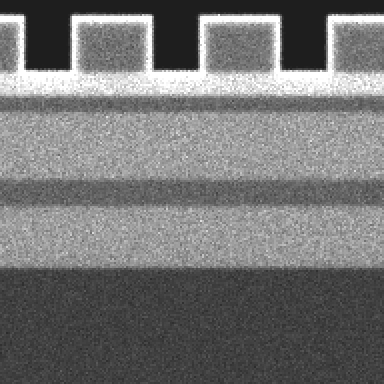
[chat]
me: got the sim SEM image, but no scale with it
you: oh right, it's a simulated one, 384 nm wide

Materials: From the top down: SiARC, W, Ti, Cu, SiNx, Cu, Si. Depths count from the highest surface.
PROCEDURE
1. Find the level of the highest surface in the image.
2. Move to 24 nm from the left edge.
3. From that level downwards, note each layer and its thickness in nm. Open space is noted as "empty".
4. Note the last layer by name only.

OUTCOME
empty 56, W 24, Ti 16, Cu 68, SiNx 26, Cu 62, Si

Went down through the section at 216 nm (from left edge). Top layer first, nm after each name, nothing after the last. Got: SiARC 56, W 24, Ti 16, Cu 68, SiNx 26, Cu 62, Si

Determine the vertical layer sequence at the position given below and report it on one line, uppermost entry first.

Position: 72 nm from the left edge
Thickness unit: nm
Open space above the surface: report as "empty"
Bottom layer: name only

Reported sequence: SiARC 56, W 24, Ti 16, Cu 68, SiNx 26, Cu 62, Si